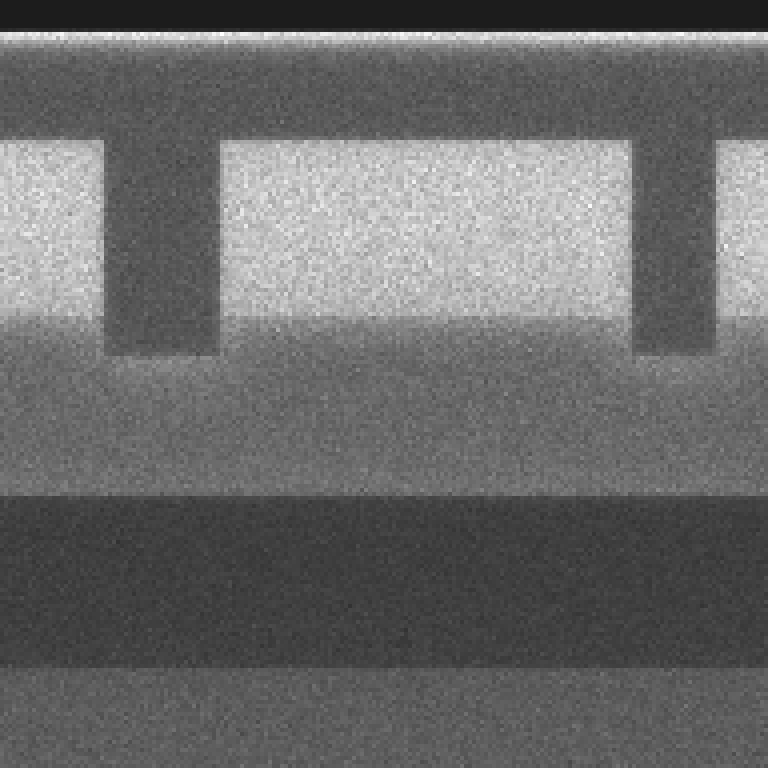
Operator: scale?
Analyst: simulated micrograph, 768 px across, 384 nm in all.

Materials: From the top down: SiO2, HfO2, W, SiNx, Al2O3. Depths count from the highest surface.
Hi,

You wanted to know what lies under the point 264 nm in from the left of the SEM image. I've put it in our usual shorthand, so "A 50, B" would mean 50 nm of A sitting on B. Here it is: SiO2 54, HfO2 88, W 90, SiNx 86, Al2O3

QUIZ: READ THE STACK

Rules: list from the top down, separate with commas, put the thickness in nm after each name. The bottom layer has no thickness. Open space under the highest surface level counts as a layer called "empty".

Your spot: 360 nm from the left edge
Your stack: SiO2 54, HfO2 88, W 90, SiNx 86, Al2O3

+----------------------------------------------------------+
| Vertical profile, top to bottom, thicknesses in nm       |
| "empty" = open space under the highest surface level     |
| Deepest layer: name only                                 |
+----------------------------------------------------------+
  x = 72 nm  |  SiO2 162, W 70, SiNx 86, Al2O3